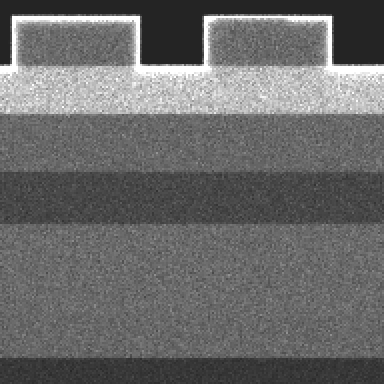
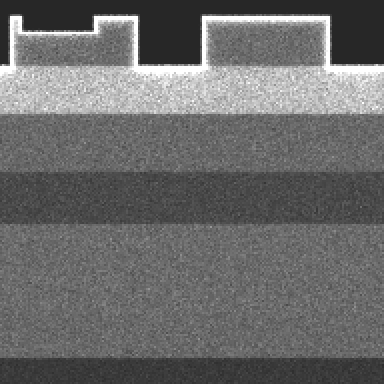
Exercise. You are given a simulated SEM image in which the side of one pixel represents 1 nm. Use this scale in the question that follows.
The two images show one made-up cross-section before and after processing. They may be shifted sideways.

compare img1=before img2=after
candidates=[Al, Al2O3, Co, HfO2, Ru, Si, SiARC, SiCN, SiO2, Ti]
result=removed:Co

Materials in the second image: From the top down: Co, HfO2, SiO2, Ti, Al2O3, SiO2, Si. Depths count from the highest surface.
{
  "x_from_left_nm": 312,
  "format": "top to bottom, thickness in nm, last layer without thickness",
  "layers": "Al2O3 50, HfO2 48, SiO2 58, Ti 52, Al2O3 90, SiO2 44, Si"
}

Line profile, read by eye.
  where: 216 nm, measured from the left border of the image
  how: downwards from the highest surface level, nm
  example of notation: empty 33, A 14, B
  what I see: Al2O3 50, HfO2 48, SiO2 58, Ti 52, Al2O3 90, SiO2 44, Si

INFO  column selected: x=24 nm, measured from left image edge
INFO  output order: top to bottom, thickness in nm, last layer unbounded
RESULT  empty 16, Co 34, HfO2 48, SiO2 58, Ti 52, Al2O3 90, SiO2 44, Si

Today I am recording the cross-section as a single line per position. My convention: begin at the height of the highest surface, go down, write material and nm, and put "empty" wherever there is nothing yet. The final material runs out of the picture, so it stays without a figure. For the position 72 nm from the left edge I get empty 16, Co 34, HfO2 48, SiO2 58, Ti 52, Al2O3 90, SiO2 44, Si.